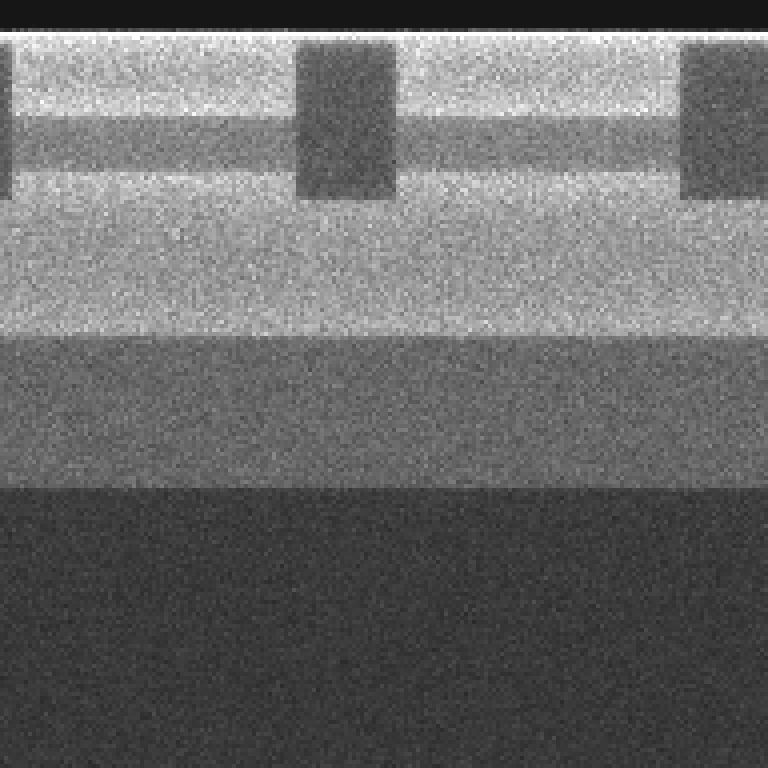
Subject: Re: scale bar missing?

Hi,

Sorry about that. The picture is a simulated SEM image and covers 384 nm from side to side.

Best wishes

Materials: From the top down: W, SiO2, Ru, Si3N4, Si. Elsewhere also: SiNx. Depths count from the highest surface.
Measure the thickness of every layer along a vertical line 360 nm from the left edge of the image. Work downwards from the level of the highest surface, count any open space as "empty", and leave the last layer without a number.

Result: SiNx 84, Ru 68, Si3N4 76, Si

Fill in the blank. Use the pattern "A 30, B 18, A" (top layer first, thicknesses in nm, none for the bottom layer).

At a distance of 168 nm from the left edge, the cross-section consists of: SiNx 84, Ru 68, Si3N4 76, Si